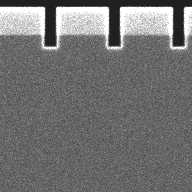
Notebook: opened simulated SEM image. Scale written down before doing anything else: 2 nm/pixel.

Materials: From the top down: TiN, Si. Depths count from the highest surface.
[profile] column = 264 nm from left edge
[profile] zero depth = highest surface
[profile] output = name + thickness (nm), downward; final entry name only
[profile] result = TiN 54, Si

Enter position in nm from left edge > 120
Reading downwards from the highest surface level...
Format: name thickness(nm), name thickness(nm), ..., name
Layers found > TiN 54, Si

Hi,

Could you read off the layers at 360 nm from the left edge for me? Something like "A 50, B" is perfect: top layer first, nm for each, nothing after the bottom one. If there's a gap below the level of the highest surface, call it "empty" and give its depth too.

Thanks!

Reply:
empty 78, Si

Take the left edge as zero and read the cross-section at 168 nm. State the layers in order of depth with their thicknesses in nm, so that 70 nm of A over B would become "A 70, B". TiN 54, Si